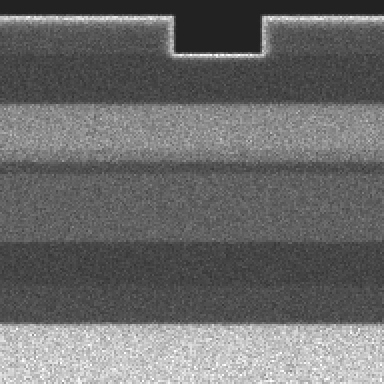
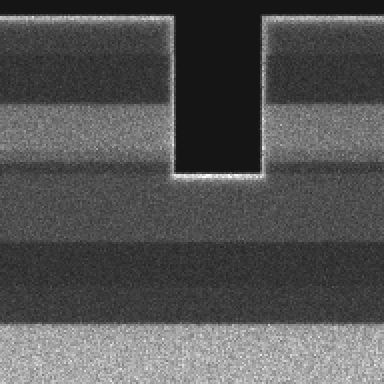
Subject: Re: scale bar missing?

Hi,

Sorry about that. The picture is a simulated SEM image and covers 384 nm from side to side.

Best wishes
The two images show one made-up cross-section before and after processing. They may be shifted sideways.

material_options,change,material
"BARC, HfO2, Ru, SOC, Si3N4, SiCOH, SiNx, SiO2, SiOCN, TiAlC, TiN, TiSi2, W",removed,Ru and SiNx and TiN and W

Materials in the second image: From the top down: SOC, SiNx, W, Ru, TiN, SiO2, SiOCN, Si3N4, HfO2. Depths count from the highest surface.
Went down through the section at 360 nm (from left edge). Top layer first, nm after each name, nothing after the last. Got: SOC 38, SiNx 50, W 46, Ru 12, TiN 12, SiO2 68, SiOCN 44, Si3N4 38, HfO2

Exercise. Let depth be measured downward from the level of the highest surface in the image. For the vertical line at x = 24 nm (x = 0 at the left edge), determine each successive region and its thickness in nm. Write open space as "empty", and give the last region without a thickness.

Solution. SOC 38, SiNx 50, W 46, Ru 12, TiN 12, SiO2 68, SiOCN 44, Si3N4 38, HfO2